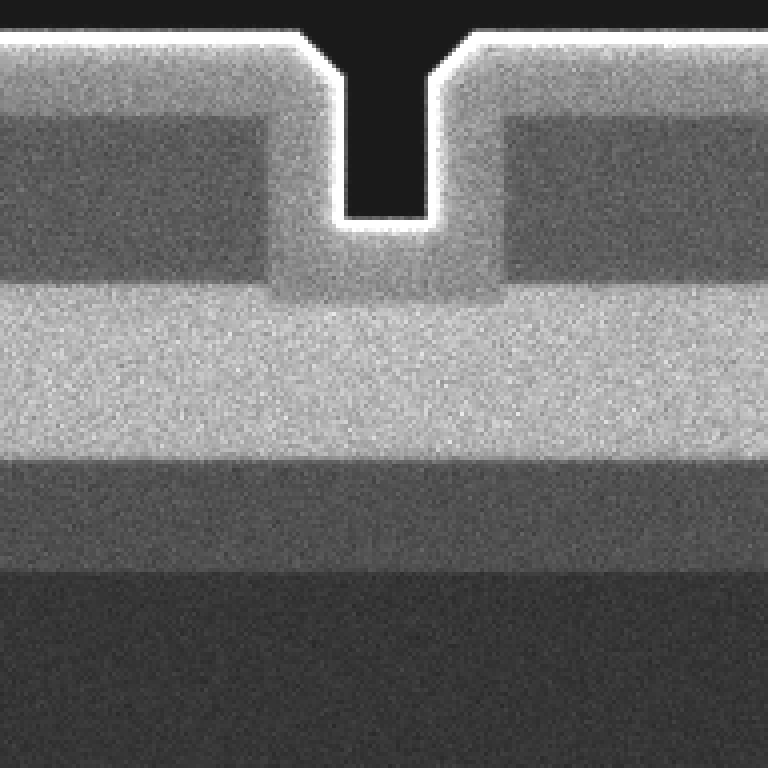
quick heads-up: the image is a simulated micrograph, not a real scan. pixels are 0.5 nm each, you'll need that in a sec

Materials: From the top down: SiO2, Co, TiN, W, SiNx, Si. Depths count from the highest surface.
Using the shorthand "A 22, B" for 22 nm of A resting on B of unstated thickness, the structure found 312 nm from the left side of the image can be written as SiO2 10, Co 32, TiN 84, W 88, SiNx 56, Si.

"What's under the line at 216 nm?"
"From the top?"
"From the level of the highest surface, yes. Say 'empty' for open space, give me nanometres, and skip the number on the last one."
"empty 20, SiO2 84, Co 32, W 78, SiNx 56, Si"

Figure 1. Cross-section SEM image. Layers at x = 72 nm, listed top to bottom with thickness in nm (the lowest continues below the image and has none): SiO2 10, Co 32, TiN 84, W 88, SiNx 56, Si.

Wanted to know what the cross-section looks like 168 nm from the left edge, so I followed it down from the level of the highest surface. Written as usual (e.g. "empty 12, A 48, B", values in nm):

empty 20, SiO2 84, Co 32, W 78, SiNx 56, Si